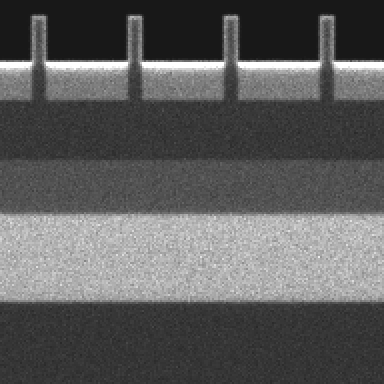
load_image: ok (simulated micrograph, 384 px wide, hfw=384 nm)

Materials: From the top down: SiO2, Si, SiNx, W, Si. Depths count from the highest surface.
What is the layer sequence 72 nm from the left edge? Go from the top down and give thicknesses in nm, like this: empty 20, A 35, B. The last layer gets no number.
empty 46, SiO2 38, Si 60, SiNx 54, W 88, Si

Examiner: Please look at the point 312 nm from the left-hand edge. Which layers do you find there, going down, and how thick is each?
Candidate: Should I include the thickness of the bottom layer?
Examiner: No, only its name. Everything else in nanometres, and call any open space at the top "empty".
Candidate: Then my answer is empty 46, SiO2 38, Si 60, SiNx 54, W 88, Si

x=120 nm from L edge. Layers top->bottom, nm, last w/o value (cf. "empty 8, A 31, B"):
empty 46, SiO2 38, Si 60, SiNx 54, W 88, Si